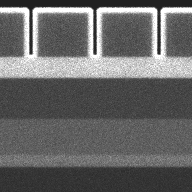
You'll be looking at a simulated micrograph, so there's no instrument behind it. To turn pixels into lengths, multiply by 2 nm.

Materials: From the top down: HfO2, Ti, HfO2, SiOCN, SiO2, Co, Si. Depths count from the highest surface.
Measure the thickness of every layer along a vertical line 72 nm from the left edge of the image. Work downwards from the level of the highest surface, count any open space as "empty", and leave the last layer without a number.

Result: HfO2 140, SiOCN 82, SiO2 72, Co 24, Si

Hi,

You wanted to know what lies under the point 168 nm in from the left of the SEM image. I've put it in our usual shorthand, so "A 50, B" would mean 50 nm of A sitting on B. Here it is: HfO2 10, Ti 88, HfO2 42, SiOCN 82, SiO2 72, Co 24, Si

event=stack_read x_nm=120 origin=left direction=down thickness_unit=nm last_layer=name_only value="HfO2 10, Ti 88, HfO2 42, SiOCN 82, SiO2 72, Co 24, Si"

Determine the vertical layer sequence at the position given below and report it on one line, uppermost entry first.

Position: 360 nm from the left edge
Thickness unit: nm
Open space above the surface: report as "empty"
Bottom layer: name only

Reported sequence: HfO2 10, Ti 88, HfO2 42, SiOCN 82, SiO2 72, Co 24, Si